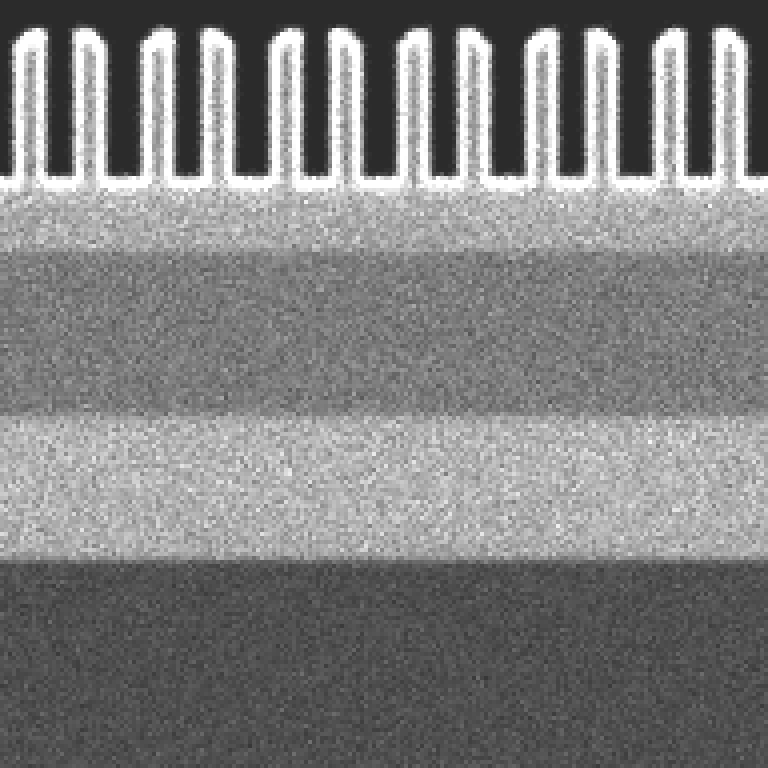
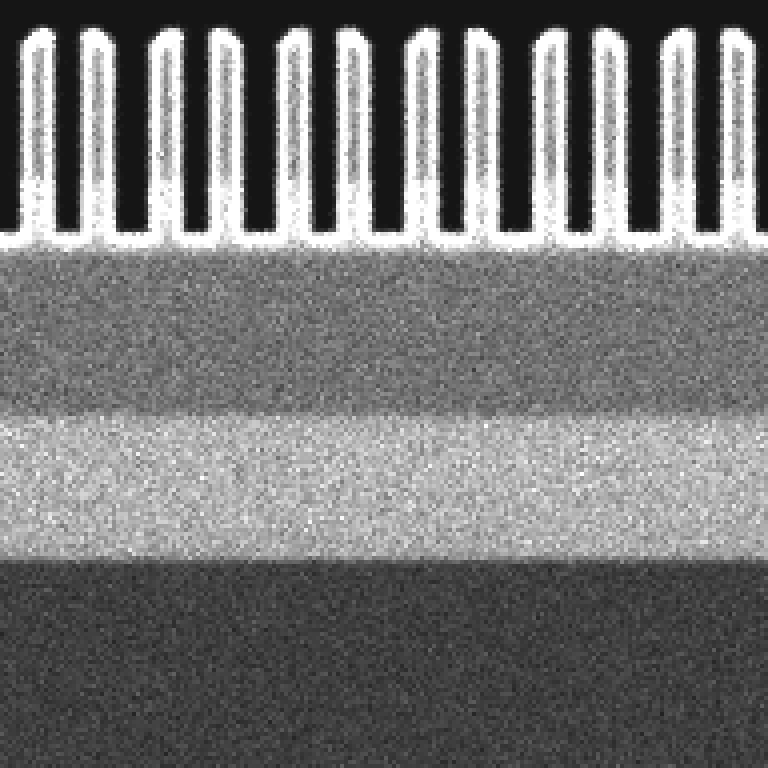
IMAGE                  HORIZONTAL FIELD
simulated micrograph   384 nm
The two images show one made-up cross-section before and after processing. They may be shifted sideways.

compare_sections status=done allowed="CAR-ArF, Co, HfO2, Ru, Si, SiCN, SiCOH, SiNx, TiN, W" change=removed material="Co"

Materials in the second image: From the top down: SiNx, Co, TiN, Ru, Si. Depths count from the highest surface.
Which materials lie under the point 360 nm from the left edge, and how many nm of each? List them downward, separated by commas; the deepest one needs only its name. empty 102, Co 8, TiN 82, Ru 72, Si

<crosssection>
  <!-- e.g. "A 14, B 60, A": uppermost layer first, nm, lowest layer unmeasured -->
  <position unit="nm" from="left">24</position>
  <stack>SiNx 74, Co 36, TiN 82, Ru 72, Si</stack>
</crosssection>